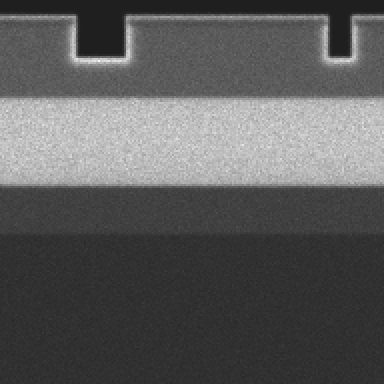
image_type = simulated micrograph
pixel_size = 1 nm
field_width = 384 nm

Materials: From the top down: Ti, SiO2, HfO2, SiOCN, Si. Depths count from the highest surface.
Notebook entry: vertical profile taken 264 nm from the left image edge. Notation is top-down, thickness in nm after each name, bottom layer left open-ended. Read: Ti 10, SiO2 72, HfO2 88, SiOCN 48, Si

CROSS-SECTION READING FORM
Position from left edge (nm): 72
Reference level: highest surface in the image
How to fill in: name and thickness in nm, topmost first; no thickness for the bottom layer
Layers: Ti 10, SiO2 72, HfO2 88, SiOCN 48, Si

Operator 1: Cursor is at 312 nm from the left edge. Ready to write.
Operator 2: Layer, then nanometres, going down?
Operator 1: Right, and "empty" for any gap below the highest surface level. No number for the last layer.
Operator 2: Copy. Ti 10, SiO2 72, HfO2 88, SiOCN 48, Si